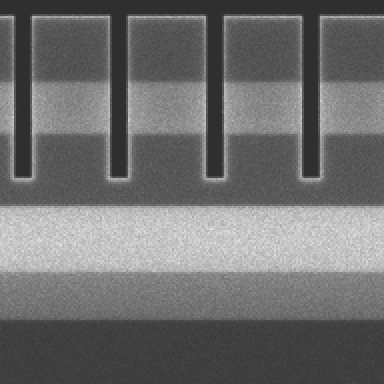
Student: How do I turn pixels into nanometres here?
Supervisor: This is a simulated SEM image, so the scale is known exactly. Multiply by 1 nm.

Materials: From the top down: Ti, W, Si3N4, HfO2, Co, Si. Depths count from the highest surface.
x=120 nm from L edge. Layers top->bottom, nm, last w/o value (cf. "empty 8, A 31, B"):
empty 162, Si3N4 28, HfO2 66, Co 48, Si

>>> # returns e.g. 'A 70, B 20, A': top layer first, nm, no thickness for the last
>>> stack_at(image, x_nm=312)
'empty 162, Si3N4 28, HfO2 66, Co 48, Si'